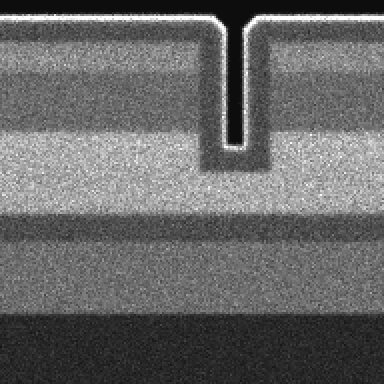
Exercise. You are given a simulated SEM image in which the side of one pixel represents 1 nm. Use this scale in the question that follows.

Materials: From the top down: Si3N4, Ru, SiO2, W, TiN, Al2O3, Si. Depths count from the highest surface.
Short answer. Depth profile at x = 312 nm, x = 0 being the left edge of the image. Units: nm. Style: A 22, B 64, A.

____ Si3N4 26, Ru 30, SiO2 60, W 82, TiN 28, Al2O3 72, Si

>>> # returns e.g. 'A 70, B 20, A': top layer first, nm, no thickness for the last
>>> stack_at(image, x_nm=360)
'Si3N4 26, Ru 30, SiO2 60, W 82, TiN 28, Al2O3 72, Si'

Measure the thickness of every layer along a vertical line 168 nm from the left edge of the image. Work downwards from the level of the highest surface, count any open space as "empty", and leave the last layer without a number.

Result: Si3N4 26, Ru 30, SiO2 60, W 82, TiN 28, Al2O3 72, Si